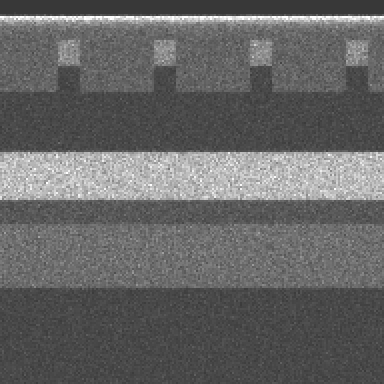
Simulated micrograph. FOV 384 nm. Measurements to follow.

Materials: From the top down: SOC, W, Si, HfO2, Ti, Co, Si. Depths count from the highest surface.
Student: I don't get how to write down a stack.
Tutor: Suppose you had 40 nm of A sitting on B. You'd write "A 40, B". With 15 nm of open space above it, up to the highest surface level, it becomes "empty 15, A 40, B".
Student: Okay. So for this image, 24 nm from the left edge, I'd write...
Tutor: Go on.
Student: SOC 76, Si 60, HfO2 48, Ti 24, Co 64, Si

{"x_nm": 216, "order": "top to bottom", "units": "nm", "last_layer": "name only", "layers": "SOC 76, Si 60, HfO2 48, Ti 24, Co 64, Si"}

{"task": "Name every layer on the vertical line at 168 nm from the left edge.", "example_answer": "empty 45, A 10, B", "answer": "SOC 24, W 26, Si 86, HfO2 48, Ti 24, Co 64, Si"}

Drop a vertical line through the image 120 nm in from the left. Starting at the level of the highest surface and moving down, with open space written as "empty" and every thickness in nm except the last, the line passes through SOC 76, Si 60, HfO2 48, Ti 24, Co 64, Si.